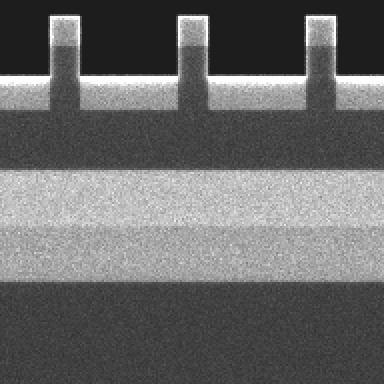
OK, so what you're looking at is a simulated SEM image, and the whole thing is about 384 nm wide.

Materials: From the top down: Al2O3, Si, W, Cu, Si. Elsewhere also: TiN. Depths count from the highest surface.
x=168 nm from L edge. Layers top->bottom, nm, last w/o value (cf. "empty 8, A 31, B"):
empty 60, Al2O3 34, Si 60, W 56, Cu 56, Si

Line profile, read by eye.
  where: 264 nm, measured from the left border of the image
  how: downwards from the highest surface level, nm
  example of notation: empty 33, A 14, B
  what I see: empty 60, Al2O3 34, Si 60, W 56, Cu 56, Si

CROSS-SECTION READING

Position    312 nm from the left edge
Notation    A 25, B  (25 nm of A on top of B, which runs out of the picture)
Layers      TiN 30, Si 124, W 56, Cu 56, Si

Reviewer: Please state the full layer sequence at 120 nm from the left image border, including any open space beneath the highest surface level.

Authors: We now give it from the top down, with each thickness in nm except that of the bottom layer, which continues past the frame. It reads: empty 60, Al2O3 34, Si 60, W 56, Cu 56, Si